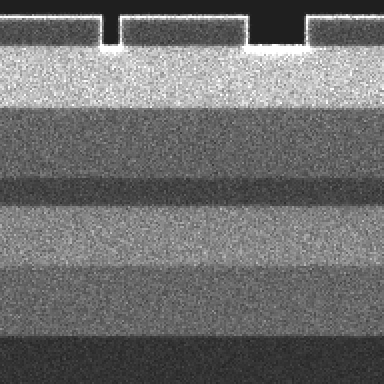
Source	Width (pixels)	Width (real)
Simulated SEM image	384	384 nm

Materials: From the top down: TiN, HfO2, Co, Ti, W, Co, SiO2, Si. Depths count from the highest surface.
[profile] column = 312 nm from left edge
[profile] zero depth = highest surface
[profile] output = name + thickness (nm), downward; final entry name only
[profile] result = TiN 30, HfO2 62, Co 70, Ti 28, W 60, Co 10, SiO2 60, Si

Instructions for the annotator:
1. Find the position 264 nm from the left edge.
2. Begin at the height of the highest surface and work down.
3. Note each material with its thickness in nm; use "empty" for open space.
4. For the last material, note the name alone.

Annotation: empty 30, HfO2 62, Co 70, Ti 28, W 60, Co 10, SiO2 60, Si